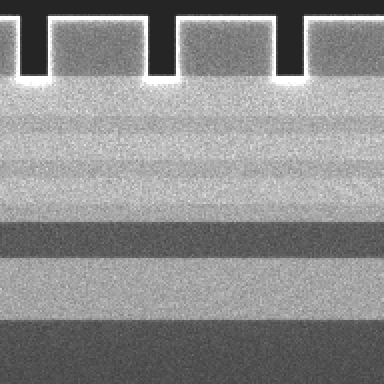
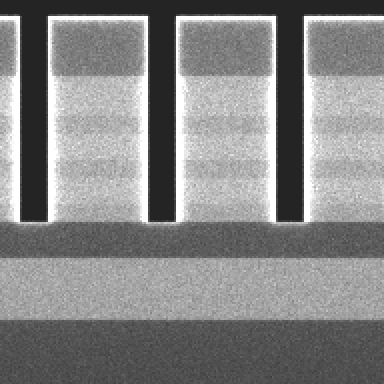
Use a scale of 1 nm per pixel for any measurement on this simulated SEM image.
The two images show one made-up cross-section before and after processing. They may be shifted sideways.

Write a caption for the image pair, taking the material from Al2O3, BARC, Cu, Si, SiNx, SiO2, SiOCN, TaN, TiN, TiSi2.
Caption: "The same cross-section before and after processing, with Al2O3 and SiO2 removed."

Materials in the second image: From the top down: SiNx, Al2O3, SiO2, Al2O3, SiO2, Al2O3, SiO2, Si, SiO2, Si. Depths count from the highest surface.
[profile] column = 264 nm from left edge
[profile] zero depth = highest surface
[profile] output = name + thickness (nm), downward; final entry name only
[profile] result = SiNx 60, Al2O3 40, SiO2 18, Al2O3 26, SiO2 18, Al2O3 26, SiO2 18, Si 36, SiO2 62, Si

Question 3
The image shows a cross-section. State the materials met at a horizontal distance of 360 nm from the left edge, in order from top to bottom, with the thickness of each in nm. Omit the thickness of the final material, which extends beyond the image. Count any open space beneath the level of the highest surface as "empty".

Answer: SiNx 60, Al2O3 40, SiO2 18, Al2O3 26, SiO2 18, Al2O3 26, SiO2 18, Si 36, SiO2 62, Si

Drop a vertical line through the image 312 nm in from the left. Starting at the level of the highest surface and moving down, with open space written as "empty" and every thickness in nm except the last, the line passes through SiNx 60, Al2O3 40, SiO2 18, Al2O3 26, SiO2 18, Al2O3 26, SiO2 18, Si 36, SiO2 62, Si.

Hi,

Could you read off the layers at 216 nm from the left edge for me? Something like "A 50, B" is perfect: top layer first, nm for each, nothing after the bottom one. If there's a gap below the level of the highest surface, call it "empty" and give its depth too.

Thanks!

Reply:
SiNx 60, Al2O3 40, SiO2 18, Al2O3 26, SiO2 18, Al2O3 26, SiO2 18, Si 36, SiO2 62, Si